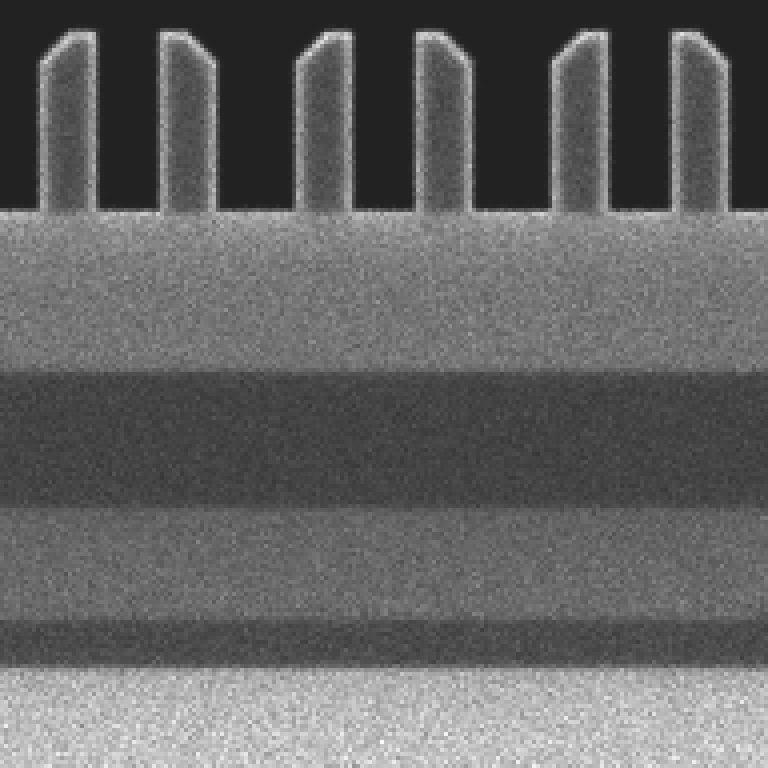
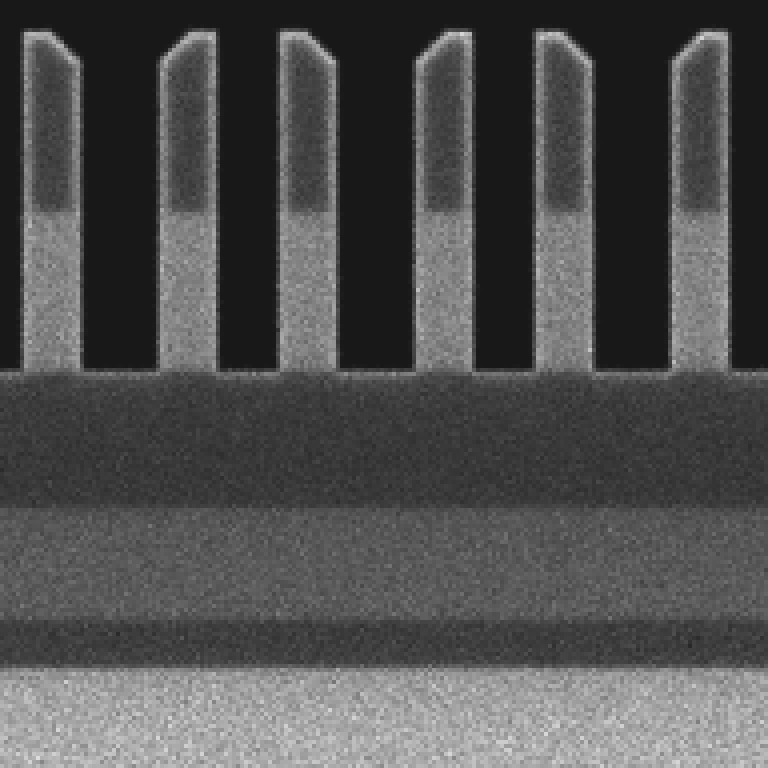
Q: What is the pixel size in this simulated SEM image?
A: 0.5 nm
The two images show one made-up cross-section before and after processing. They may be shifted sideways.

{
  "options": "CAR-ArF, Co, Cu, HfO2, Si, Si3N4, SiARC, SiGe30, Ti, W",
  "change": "removed",
  "material": "W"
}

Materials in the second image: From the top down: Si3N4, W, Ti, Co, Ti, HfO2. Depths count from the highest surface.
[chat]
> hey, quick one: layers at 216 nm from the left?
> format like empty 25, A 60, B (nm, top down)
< empty 6, Si3N4 84, W 80, Ti 68, Co 56, Ti 24, HfO2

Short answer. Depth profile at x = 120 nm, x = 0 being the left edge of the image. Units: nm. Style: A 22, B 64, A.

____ empty 170, Ti 68, Co 56, Ti 24, HfO2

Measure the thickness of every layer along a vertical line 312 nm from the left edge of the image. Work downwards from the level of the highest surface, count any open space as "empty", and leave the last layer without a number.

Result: empty 170, Ti 68, Co 56, Ti 24, HfO2